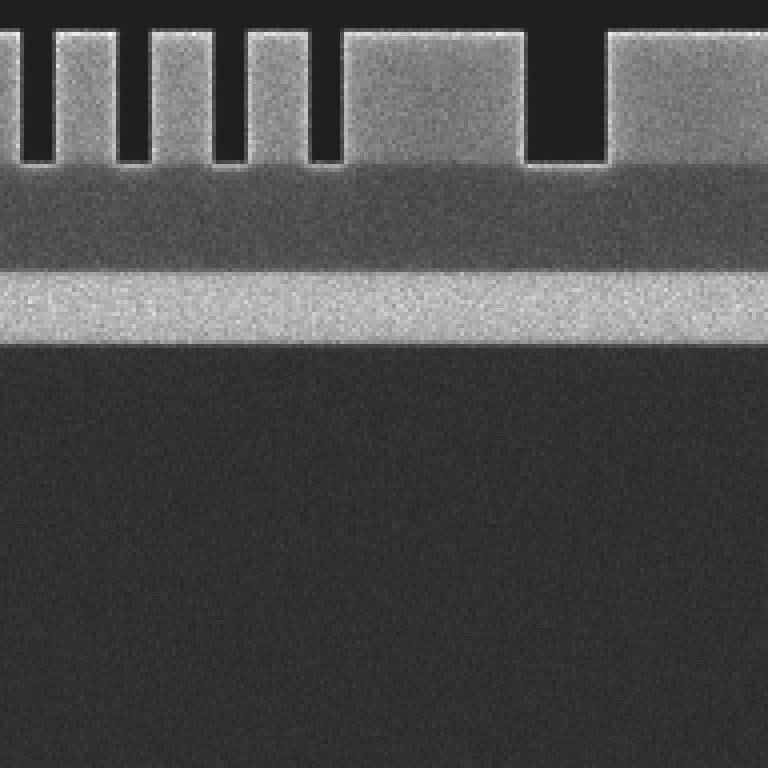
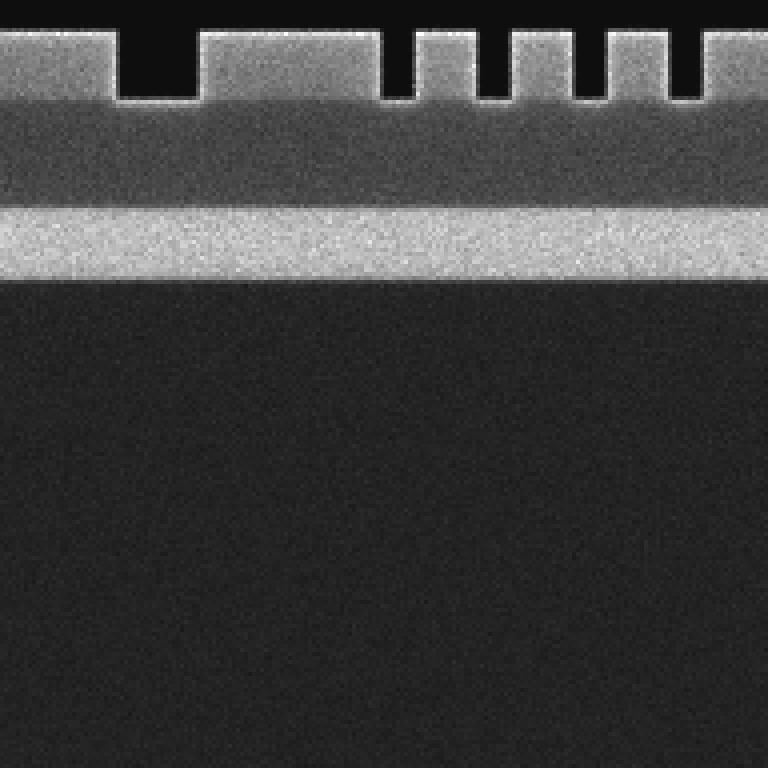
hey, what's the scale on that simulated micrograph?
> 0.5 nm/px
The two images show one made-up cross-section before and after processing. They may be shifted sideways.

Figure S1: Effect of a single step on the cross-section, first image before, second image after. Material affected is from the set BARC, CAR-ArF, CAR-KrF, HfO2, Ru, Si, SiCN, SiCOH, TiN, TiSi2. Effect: removed Ru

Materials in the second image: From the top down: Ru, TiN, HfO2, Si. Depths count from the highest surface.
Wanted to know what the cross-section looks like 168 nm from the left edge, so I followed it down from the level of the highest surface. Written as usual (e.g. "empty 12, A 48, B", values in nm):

Ru 34, TiN 54, HfO2 36, Si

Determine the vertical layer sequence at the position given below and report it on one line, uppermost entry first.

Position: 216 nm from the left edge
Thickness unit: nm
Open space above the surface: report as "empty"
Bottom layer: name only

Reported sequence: Ru 34, TiN 54, HfO2 36, Si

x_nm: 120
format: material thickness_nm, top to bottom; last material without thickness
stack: Ru 34, TiN 54, HfO2 36, Si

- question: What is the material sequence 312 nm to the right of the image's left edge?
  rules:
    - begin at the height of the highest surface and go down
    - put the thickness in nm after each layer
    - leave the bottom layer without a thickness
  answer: Ru 34, TiN 54, HfO2 36, Si